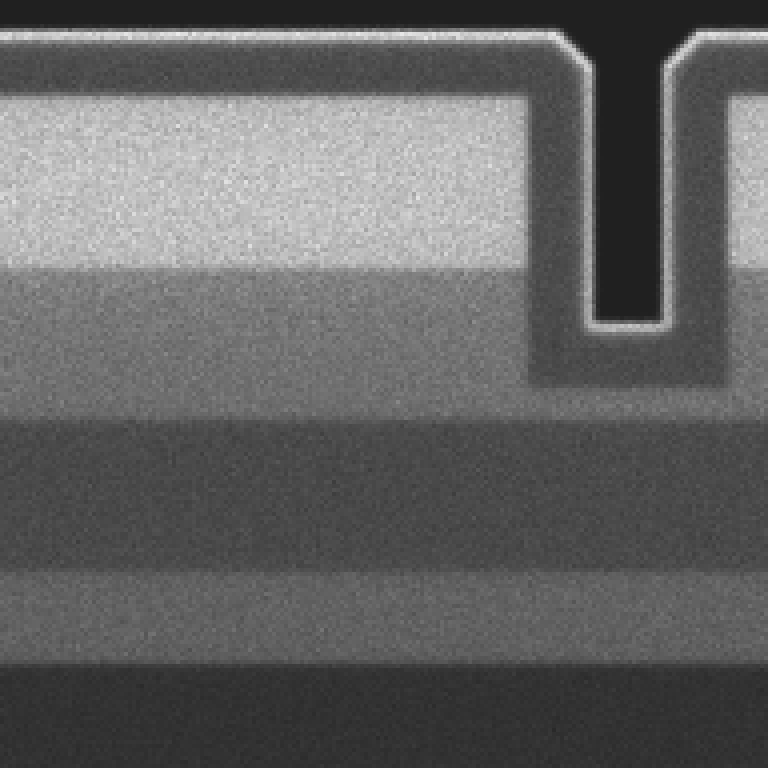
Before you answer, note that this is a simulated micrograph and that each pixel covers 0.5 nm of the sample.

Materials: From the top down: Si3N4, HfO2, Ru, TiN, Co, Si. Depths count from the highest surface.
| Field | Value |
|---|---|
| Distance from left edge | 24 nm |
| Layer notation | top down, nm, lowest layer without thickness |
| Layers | Si3N4 32, HfO2 86, Ru 76, TiN 76, Co 46, Si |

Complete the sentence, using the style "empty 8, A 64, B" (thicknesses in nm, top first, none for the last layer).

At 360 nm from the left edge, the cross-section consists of Si3N4 178, Ru 16, TiN 76, Co 46, Si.